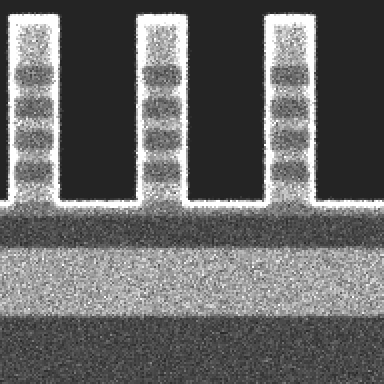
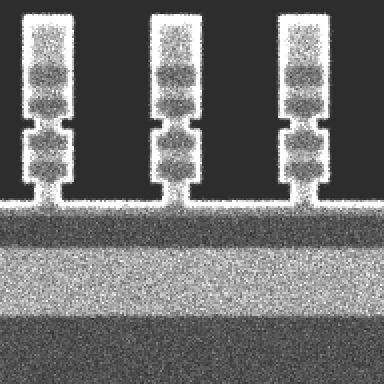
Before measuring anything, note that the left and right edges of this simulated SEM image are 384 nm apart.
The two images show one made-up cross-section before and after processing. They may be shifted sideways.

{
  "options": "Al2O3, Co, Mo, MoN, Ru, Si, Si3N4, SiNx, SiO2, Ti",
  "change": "removed",
  "material": "Co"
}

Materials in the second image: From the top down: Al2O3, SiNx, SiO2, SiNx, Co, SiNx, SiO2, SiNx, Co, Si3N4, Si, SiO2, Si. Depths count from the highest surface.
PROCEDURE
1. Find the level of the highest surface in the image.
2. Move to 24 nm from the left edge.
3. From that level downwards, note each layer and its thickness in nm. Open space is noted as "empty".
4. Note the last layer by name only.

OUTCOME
Al2O3 50, SiNx 20, SiO2 12, SiNx 20, empty 12, SiNx 20, SiO2 12, SiNx 20, empty 20, Si3N4 14, Si 32, SiO2 68, Si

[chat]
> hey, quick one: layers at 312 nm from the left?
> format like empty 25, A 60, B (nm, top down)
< Al2O3 50, SiNx 20, SiO2 12, SiNx 20, Co 12, SiNx 20, SiO2 12, SiNx 20, Co 20, Si3N4 14, Si 32, SiO2 68, Si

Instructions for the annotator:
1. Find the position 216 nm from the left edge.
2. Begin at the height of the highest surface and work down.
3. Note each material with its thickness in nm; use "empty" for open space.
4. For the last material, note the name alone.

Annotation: empty 186, Si3N4 14, Si 32, SiO2 68, Si